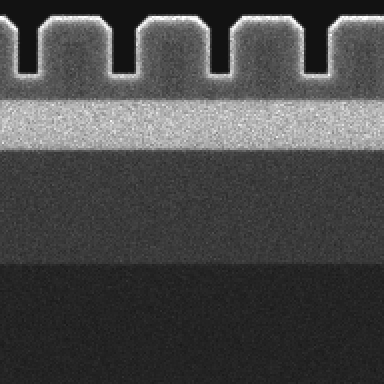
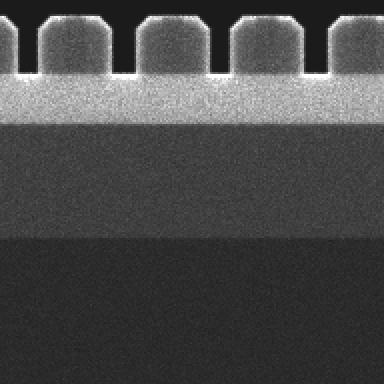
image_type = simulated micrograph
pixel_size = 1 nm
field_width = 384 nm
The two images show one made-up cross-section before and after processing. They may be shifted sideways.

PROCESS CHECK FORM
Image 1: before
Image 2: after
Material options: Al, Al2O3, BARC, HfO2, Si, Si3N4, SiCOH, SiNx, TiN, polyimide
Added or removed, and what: removed, Al2O3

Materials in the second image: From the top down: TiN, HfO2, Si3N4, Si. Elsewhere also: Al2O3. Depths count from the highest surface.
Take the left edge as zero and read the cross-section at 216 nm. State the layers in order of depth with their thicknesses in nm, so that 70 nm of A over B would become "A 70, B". empty 58, HfO2 50, Si3N4 114, Si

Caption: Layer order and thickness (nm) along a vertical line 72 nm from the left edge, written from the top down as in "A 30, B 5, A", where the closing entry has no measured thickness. TiN 58, HfO2 50, Si3N4 114, Si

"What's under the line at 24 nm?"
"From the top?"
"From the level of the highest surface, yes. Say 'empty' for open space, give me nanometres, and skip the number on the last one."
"empty 58, HfO2 50, Si3N4 114, Si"